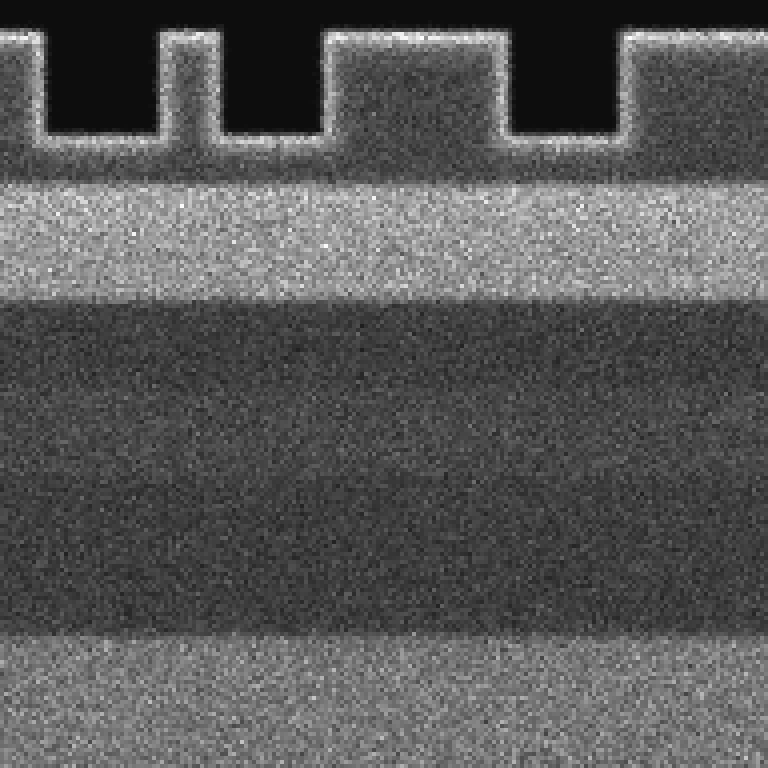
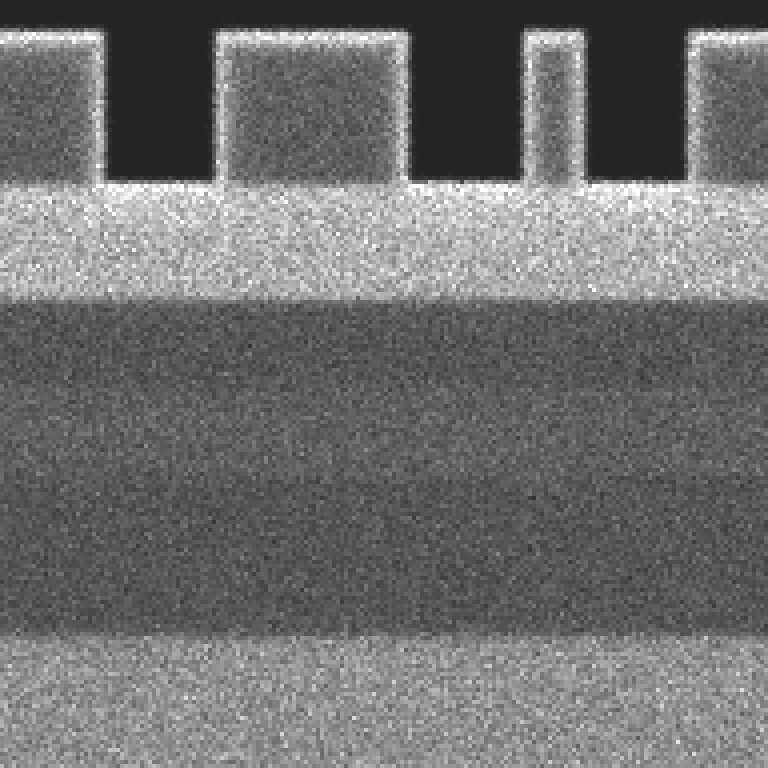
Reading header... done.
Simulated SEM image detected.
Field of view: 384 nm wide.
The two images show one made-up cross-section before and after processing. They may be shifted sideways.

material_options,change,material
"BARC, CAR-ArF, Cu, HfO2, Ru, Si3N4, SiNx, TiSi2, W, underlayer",removed,underlayer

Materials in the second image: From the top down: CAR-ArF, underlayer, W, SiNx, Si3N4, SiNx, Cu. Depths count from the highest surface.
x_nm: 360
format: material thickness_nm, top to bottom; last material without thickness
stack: CAR-ArF 52, underlayer 24, W 58, SiNx 44, Si3N4 44, SiNx 80, Cu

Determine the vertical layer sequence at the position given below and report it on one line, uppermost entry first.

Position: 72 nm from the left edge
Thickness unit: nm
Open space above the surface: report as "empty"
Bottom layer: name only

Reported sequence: empty 76, W 58, SiNx 44, Si3N4 44, SiNx 80, Cu